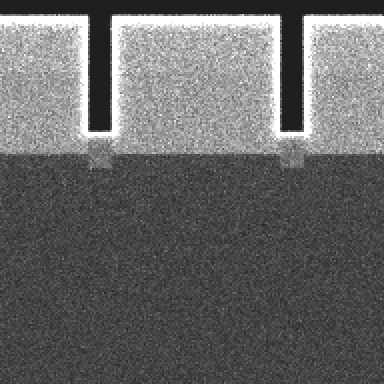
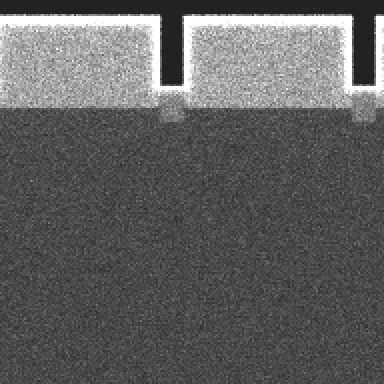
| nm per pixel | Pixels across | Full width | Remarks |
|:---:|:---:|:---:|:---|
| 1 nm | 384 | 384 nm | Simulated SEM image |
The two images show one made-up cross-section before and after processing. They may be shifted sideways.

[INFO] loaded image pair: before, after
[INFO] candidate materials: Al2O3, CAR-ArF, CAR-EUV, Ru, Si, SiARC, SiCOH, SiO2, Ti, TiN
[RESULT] removed Al2O3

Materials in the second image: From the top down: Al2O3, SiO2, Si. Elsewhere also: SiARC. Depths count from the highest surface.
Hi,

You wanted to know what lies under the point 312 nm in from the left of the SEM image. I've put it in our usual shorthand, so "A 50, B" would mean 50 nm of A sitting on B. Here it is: Al2O3 10, SiO2 82, Si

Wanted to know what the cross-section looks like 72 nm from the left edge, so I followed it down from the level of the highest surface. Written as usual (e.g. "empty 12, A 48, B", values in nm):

Al2O3 10, SiO2 82, Si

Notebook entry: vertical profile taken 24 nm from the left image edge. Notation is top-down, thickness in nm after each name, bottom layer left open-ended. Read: Al2O3 10, SiO2 82, Si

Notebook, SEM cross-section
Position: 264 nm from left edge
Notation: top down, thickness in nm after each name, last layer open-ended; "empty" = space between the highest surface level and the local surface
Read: Al2O3 10, SiO2 82, Si